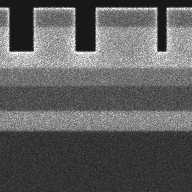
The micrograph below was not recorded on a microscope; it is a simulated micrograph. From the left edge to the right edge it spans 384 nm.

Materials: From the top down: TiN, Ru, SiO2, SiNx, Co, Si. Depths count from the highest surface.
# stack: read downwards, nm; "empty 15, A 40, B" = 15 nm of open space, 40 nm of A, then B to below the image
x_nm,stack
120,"TiN 38, Ru 82, SiO2 36, SiNx 50, Co 40, Si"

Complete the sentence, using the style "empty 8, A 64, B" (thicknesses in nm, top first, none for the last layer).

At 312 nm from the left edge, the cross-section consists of TiN 38, Ru 82, SiO2 36, SiNx 50, Co 40, Si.